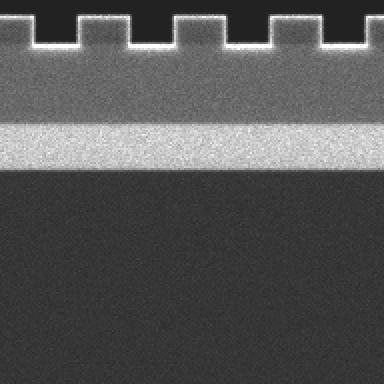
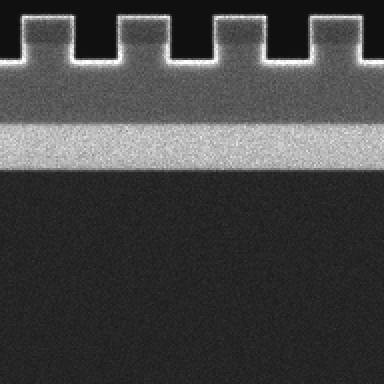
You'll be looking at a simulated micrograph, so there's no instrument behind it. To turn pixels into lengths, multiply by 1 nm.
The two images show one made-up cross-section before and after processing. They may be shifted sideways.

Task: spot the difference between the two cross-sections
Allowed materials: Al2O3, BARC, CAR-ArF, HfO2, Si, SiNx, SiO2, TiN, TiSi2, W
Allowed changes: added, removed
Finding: removed SiO2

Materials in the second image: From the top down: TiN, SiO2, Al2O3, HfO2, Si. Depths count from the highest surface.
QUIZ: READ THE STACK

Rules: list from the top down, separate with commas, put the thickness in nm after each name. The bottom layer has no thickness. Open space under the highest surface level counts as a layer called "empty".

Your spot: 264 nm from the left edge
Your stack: TiN 28, SiO2 70, Al2O3 10, HfO2 46, Si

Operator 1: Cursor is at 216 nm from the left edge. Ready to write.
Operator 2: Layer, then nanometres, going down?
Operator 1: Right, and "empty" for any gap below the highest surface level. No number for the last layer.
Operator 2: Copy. TiN 28, SiO2 70, Al2O3 10, HfO2 46, Si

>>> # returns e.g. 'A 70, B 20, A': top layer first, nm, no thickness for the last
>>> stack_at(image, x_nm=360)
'TiN 28, SiO2 70, Al2O3 10, HfO2 46, Si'